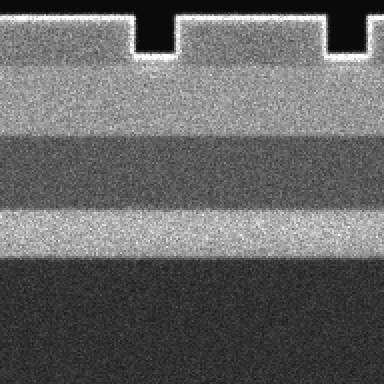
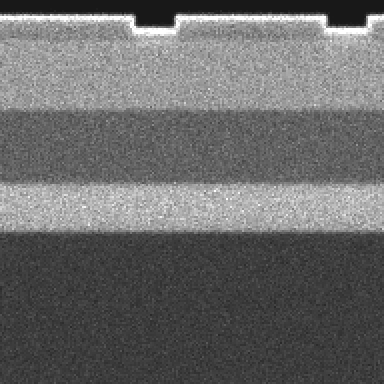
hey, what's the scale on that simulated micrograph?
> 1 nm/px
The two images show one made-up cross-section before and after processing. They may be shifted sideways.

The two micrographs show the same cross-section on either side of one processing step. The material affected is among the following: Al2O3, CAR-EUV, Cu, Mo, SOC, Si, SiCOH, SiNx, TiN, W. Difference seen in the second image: TiN removed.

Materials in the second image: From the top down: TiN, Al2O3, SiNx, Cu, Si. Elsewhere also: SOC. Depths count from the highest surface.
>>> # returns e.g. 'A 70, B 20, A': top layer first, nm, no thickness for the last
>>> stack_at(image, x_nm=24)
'TiN 24, Al2O3 70, SiNx 74, Cu 48, Si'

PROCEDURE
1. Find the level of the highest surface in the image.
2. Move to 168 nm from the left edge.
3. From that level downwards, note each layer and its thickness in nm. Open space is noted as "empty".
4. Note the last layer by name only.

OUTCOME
empty 12, SOC 12, Al2O3 70, SiNx 74, Cu 48, Si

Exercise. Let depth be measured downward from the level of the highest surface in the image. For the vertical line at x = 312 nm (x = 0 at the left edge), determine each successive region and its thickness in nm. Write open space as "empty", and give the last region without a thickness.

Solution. TiN 24, Al2O3 70, SiNx 74, Cu 48, Si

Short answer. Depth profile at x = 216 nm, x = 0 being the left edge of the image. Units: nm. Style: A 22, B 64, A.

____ TiN 24, Al2O3 70, SiNx 74, Cu 48, Si